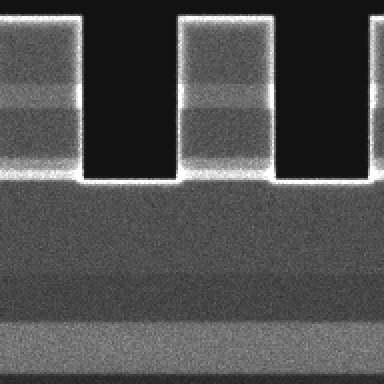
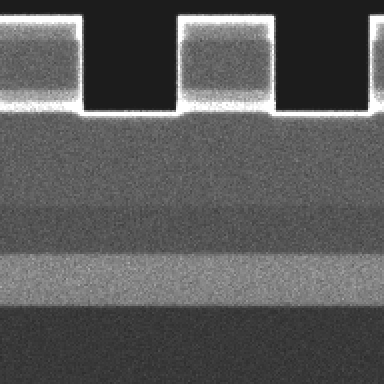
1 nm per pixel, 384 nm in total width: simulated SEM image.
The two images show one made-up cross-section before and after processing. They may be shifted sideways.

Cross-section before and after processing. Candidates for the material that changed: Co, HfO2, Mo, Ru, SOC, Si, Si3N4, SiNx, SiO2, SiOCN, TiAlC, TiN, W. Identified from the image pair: SOC (removed).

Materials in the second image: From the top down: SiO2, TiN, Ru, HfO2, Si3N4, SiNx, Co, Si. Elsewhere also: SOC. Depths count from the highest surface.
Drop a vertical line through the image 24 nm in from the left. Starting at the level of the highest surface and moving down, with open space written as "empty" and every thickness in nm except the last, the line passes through SiO2 24, TiN 50, Ru 12, HfO2 10, Si3N4 94, SiNx 48, Co 52, Si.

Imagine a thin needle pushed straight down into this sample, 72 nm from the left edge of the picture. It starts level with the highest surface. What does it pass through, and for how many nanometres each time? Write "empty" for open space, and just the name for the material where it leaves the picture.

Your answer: SiO2 24, TiN 50, Ru 12, HfO2 10, Si3N4 94, SiNx 48, Co 52, Si